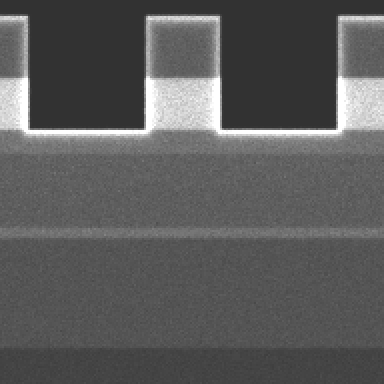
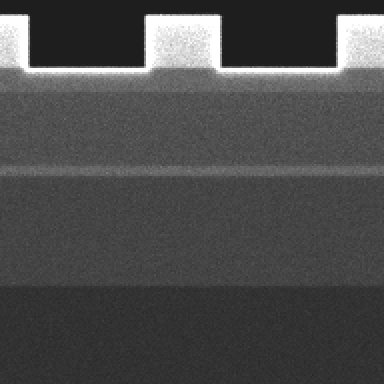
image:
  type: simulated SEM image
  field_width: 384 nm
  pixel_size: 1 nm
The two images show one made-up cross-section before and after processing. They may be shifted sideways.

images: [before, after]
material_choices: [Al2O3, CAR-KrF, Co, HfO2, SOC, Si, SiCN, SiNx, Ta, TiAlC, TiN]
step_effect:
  removed: SOC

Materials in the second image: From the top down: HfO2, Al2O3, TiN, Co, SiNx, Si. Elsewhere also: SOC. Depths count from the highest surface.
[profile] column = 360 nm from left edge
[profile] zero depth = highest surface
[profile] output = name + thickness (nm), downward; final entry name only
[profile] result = HfO2 52, Al2O3 24, TiN 74, Co 10, SiNx 110, Si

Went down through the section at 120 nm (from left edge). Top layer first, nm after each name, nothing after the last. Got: empty 52, Al2O3 24, TiN 74, Co 10, SiNx 110, Si